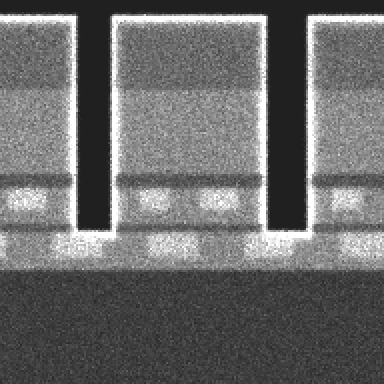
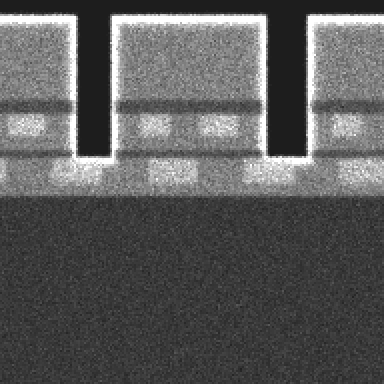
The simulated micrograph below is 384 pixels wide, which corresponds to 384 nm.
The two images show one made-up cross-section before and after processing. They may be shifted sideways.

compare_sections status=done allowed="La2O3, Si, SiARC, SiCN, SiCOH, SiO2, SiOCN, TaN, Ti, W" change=removed material="SiARC"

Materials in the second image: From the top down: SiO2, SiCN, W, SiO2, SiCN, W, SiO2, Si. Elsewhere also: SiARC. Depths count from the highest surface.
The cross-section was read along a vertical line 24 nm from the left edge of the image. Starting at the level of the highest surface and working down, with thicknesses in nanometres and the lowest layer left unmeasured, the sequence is SiO2 84, SiCN 14, W 22, SiO2 14, SiCN 8, SiO2 38, Si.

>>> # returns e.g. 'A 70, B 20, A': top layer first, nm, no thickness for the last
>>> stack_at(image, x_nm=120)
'SiO2 84, SiCN 14, SiO2 36, SiCN 8, SiO2 38, Si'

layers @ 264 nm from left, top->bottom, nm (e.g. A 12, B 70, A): SiO2 84, SiCN 14, SiO2 36, SiCN 8, W 26, SiO2 12, Si